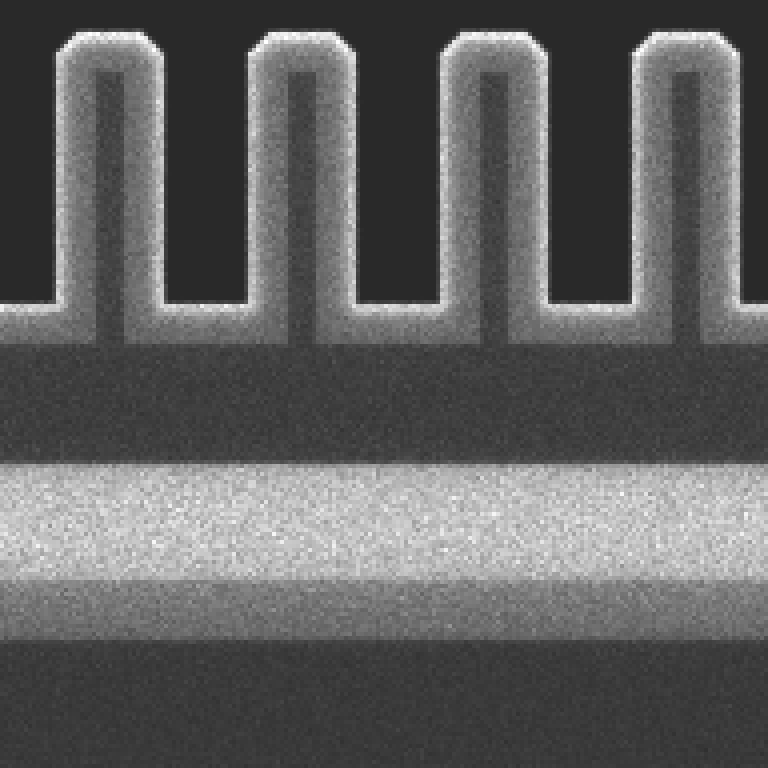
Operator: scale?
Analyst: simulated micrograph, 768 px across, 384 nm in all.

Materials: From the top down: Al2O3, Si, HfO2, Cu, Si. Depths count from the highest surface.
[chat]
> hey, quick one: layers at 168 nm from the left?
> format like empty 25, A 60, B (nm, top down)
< empty 2, Al2O3 154, Si 60, HfO2 58, Cu 30, Si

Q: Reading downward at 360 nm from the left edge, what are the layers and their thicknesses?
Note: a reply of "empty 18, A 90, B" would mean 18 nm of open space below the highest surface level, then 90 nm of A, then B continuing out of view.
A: empty 2, Al2O3 154, Si 60, HfO2 58, Cu 30, Si